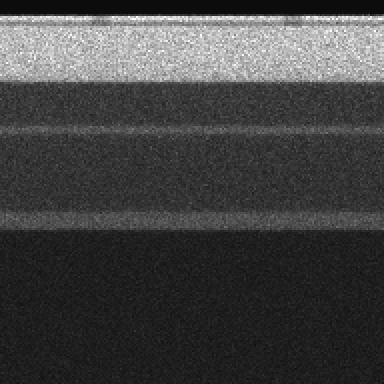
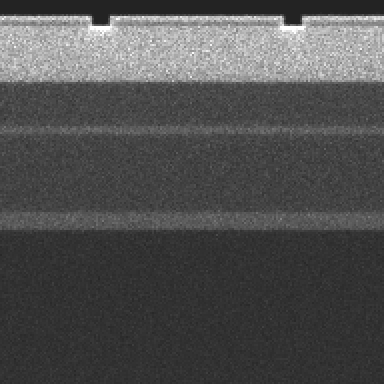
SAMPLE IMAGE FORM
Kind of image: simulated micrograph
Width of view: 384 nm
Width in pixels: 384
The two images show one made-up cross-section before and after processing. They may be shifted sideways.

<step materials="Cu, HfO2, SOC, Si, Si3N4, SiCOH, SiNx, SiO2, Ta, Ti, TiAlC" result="removed SOC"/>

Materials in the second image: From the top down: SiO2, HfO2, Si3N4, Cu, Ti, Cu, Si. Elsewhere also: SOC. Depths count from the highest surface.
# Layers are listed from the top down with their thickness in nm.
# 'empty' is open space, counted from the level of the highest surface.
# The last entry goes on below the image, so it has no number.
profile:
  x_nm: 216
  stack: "SiO2 10, HfO2 56, Si3N4 44, Cu 8, Ti 78, Cu 18, Si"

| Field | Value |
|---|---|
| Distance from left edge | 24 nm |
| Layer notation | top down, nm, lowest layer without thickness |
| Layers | SiO2 10, HfO2 56, Si3N4 44, Cu 8, Ti 78, Cu 18, Si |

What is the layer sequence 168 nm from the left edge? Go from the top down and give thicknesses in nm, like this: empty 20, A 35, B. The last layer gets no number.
SiO2 10, HfO2 56, Si3N4 44, Cu 8, Ti 78, Cu 18, Si